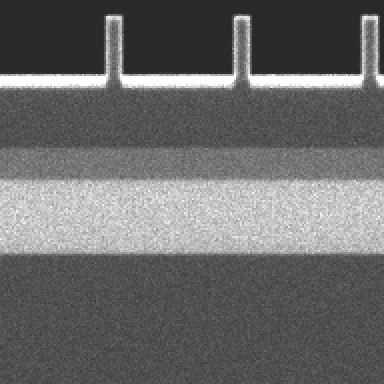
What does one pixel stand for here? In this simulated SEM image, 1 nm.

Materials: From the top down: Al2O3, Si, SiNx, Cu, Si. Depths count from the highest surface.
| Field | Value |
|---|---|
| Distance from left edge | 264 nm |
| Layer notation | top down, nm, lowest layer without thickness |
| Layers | empty 60, Al2O3 12, Si 60, SiNx 32, Cu 74, Si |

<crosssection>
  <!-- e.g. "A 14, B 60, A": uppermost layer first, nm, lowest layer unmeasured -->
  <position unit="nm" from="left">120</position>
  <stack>Si 132, SiNx 32, Cu 74, Si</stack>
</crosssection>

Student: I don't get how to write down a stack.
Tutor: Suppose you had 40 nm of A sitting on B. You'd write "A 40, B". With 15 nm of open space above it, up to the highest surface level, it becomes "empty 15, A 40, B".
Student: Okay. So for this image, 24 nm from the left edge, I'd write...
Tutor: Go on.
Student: empty 60, Al2O3 12, Si 60, SiNx 32, Cu 74, Si